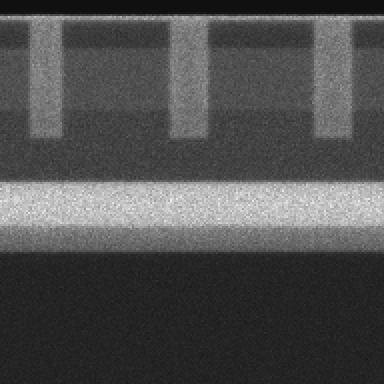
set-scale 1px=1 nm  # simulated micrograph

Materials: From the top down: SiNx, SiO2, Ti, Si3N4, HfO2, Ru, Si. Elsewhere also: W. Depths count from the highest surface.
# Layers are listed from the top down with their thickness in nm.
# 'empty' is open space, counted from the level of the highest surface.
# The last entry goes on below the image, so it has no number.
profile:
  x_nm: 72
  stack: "SiNx 32, SiO2 62, Ti 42, Si3N4 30, HfO2 44, Ru 26, Si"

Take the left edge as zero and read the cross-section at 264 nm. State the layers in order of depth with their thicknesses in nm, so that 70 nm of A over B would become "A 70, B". SiNx 32, SiO2 62, Ti 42, Si3N4 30, HfO2 44, Ru 26, Si